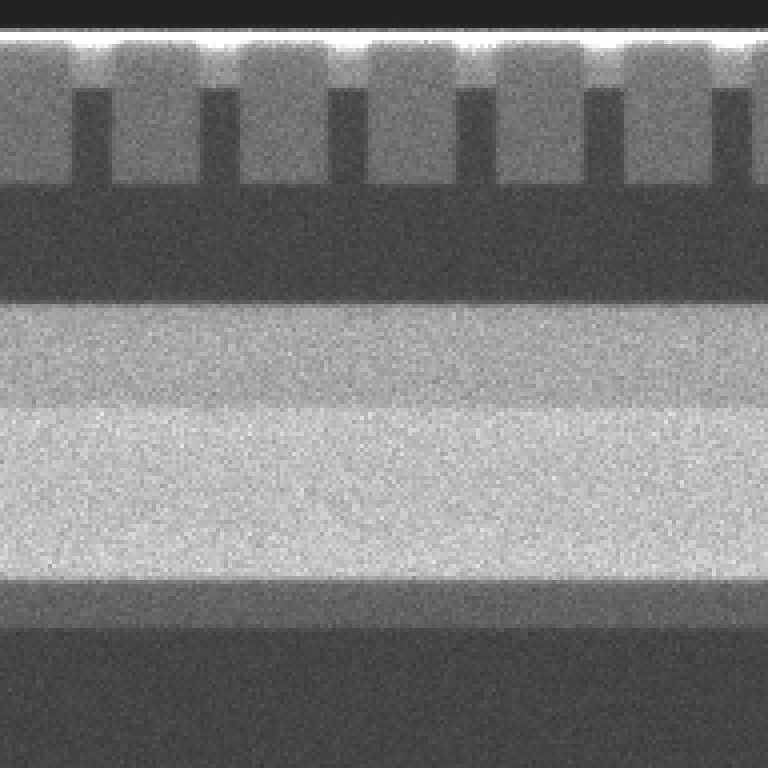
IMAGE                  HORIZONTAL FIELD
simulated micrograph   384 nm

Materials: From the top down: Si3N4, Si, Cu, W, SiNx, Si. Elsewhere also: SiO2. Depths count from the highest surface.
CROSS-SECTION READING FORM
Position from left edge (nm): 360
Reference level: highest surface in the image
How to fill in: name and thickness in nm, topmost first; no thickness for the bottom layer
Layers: SiO2 28, Si 108, Cu 52, W 86, SiNx 24, Si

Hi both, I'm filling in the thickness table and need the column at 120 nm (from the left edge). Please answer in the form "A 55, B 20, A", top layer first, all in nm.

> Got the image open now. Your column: Si3N4 76, Si 60, Cu 52, W 86, SiNx 24, Si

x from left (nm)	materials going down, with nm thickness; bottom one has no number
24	Si3N4 76, Si 60, Cu 52, W 86, SiNx 24, Si